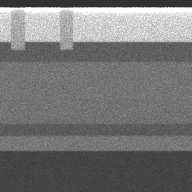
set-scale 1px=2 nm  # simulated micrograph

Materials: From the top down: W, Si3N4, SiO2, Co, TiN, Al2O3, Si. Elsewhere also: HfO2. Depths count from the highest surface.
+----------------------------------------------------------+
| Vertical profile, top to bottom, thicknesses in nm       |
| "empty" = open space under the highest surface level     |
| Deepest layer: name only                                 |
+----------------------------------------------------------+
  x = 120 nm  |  W 84, Si3N4 24, SiO2 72, Co 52, TiN 24, Al2O3 30, Si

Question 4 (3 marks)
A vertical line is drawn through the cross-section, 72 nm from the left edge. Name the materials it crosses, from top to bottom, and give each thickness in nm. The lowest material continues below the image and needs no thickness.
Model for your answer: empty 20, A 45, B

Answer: HfO2 68, Si3N4 40, SiO2 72, Co 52, TiN 24, Al2O3 30, Si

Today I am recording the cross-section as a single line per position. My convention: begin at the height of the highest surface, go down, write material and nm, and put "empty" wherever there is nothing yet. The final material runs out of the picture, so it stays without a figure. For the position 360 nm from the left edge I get HfO2 68, Si3N4 40, SiO2 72, Co 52, TiN 24, Al2O3 30, Si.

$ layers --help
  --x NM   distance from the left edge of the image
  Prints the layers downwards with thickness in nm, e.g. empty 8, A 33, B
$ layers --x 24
W 84, Si3N4 24, SiO2 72, Co 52, TiN 24, Al2O3 30, Si